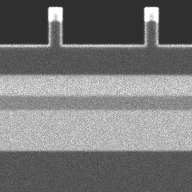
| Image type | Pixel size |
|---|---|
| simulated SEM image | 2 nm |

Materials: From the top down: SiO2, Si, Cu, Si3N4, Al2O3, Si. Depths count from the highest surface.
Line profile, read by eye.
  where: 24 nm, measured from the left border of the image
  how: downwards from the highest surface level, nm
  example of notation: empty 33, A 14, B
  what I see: empty 74, Si 60, Cu 42, Si3N4 28, Al2O3 82, Si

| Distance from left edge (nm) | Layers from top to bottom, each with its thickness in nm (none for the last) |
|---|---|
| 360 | empty 74, Si 60, Cu 42, Si3N4 28, Al2O3 82, Si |